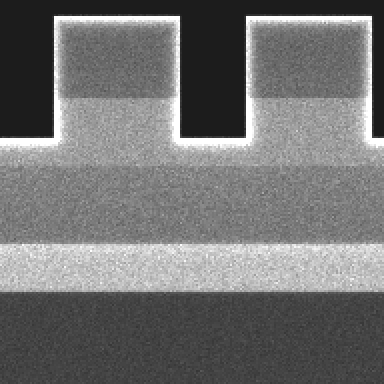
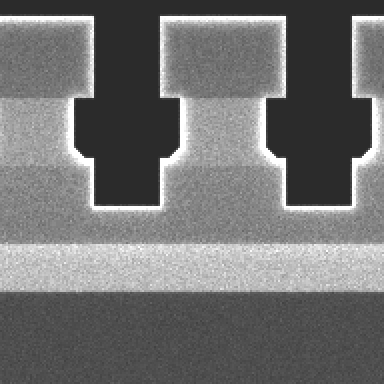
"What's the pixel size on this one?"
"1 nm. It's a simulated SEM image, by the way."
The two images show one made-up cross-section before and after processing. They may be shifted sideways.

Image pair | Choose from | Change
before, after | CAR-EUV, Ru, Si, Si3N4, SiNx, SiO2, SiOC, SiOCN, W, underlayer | Si3N4 and SiO2 (removed)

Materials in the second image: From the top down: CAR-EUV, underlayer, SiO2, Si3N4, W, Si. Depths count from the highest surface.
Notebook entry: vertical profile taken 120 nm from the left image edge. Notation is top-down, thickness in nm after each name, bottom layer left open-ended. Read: empty 190, Si3N4 38, W 48, Si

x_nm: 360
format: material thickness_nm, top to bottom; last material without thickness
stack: CAR-EUV 56, underlayer 26, empty 60, SiO2 8, Si3N4 78, W 48, Si